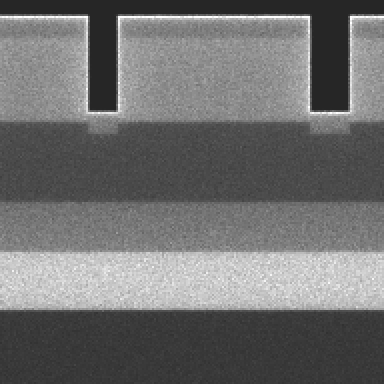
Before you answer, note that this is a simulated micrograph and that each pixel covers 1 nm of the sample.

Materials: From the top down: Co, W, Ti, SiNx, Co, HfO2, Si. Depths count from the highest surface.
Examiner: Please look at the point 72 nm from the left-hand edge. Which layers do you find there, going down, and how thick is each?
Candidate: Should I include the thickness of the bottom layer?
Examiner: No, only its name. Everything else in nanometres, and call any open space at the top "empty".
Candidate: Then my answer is Co 22, W 84, Ti 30, SiNx 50, Co 50, HfO2 58, Si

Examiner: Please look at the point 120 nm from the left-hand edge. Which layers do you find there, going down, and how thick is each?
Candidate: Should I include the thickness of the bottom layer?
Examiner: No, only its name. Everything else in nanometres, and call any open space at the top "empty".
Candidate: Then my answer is Co 22, W 84, Ti 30, SiNx 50, Co 50, HfO2 58, Si